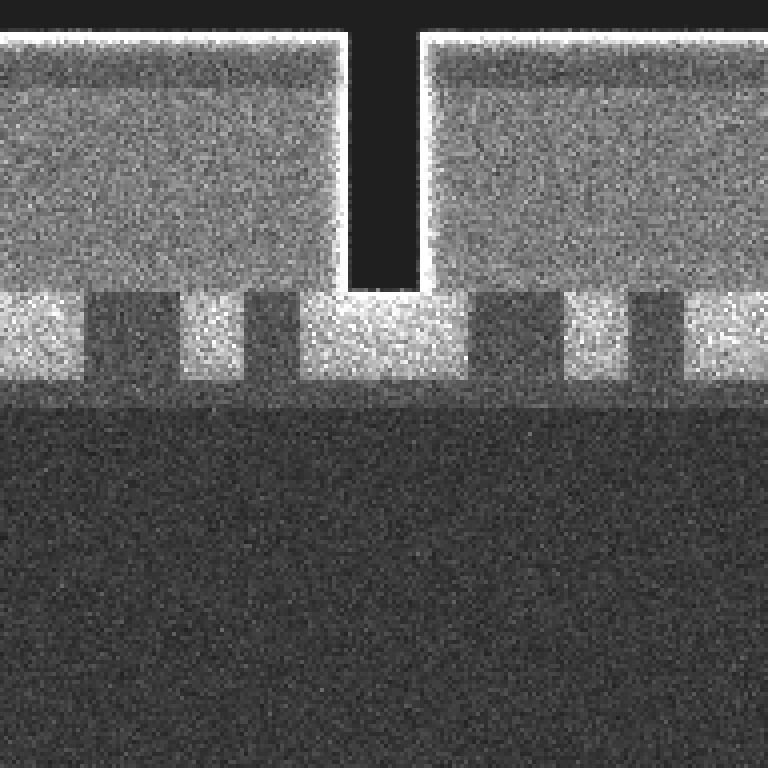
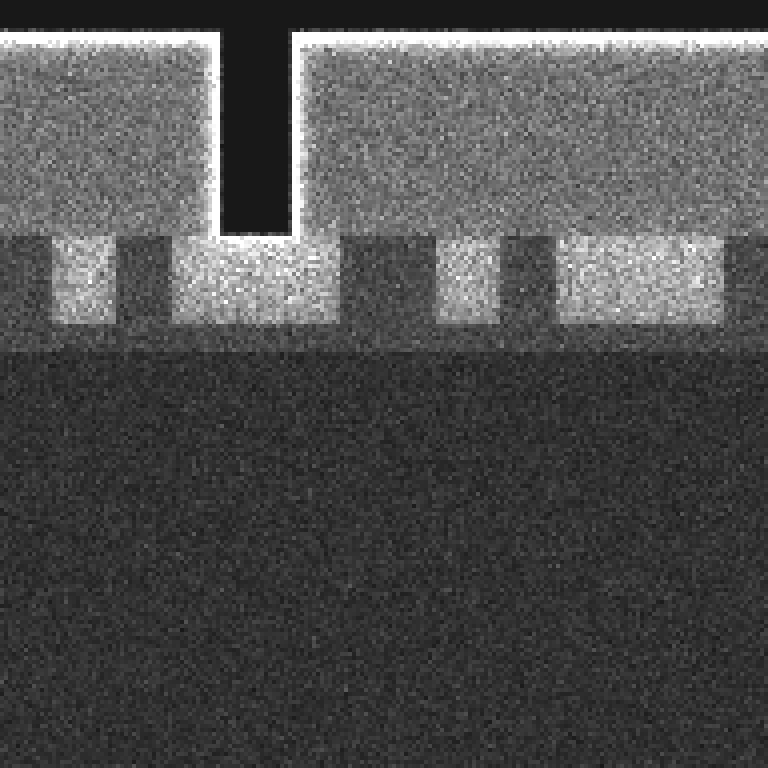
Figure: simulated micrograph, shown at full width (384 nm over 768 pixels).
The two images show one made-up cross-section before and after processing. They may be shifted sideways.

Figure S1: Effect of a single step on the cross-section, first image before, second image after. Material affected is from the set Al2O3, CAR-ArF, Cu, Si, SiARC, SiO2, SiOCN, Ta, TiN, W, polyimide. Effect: removed SiARC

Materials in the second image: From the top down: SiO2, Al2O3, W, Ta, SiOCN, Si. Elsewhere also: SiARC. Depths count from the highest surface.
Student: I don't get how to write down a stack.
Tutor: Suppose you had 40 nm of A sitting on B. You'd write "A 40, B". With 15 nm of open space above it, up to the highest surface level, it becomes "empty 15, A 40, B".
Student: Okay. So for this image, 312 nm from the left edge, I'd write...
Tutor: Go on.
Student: SiO2 86, Al2O3 16, W 36, Ta 8, SiOCN 14, Si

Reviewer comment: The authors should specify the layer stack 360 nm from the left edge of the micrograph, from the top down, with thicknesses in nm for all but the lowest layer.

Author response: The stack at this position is SiO2 86, Al2O3 16, Ta 44, SiOCN 14, Si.